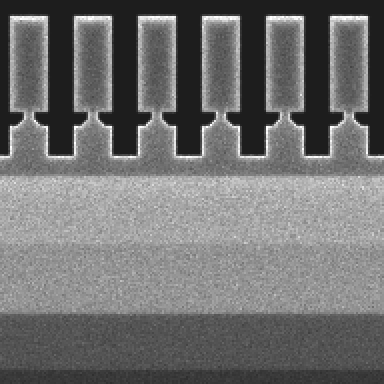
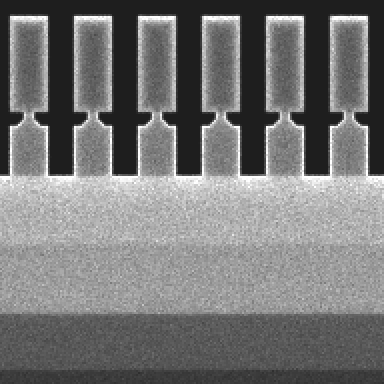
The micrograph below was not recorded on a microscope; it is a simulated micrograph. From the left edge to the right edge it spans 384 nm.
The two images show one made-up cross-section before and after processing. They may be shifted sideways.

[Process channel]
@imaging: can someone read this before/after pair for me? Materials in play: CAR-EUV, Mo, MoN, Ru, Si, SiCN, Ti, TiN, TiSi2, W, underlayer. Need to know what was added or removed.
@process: TiN removed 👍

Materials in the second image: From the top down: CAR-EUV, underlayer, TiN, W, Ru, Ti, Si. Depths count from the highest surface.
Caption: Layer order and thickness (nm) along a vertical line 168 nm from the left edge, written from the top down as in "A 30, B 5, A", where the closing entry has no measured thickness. CAR-EUV 64, underlayer 32, empty 14, TiN 50, W 68, Ru 70, Ti 56, Si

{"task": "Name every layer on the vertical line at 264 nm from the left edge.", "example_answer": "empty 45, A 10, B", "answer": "empty 160, W 68, Ru 70, Ti 56, Si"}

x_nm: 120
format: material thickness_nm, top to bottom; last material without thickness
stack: empty 160, W 68, Ru 70, Ti 56, Si